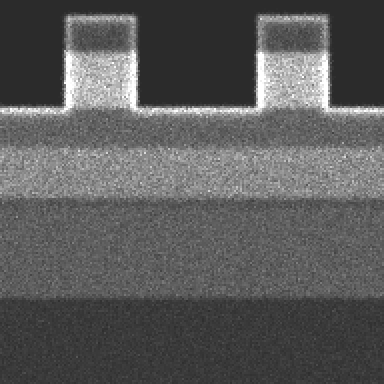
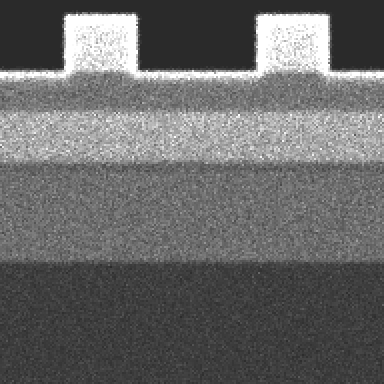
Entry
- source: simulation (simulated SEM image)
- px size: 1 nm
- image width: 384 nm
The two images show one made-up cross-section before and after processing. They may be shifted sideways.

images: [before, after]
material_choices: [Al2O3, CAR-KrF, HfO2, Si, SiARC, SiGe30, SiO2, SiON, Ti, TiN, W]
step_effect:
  removed: SiARC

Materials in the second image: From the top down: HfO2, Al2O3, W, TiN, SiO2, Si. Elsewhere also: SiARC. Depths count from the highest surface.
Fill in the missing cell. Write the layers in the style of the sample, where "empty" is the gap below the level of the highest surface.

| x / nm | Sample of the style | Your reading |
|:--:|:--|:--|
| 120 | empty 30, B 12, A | HfO2 56, Al2O3 40, W 50, TiN 10, SiO2 90, Si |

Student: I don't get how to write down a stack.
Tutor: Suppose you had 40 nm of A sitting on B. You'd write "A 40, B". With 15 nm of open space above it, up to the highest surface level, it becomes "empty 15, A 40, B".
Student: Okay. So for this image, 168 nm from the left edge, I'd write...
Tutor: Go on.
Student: empty 56, Al2O3 40, W 50, TiN 10, SiO2 90, Si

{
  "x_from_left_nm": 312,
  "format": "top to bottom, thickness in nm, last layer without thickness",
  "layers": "HfO2 56, Al2O3 40, W 50, TiN 10, SiO2 90, Si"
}